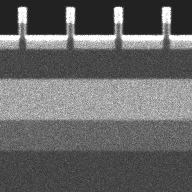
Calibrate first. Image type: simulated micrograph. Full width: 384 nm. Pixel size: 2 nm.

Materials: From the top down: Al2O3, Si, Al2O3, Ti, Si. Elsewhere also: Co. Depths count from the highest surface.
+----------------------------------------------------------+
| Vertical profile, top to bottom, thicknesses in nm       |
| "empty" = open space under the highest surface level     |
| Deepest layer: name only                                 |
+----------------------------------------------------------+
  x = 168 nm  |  empty 56, Al2O3 26, Si 60, Al2O3 82, Ti 62, Si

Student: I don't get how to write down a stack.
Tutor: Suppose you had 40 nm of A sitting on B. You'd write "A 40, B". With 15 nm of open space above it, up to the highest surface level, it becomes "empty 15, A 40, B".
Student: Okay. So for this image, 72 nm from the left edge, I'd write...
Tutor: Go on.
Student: empty 56, Al2O3 26, Si 60, Al2O3 82, Ti 62, Si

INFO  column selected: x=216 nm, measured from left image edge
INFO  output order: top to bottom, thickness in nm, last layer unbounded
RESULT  empty 56, Al2O3 26, Si 60, Al2O3 82, Ti 62, Si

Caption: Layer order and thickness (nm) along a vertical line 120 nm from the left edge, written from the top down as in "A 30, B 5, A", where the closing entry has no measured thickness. empty 56, Al2O3 26, Si 60, Al2O3 82, Ti 62, Si